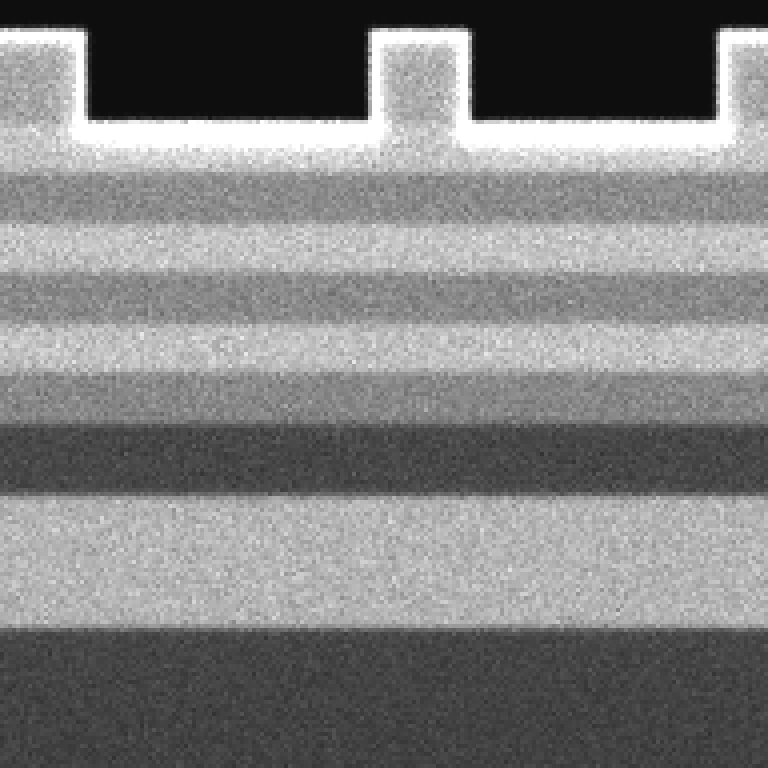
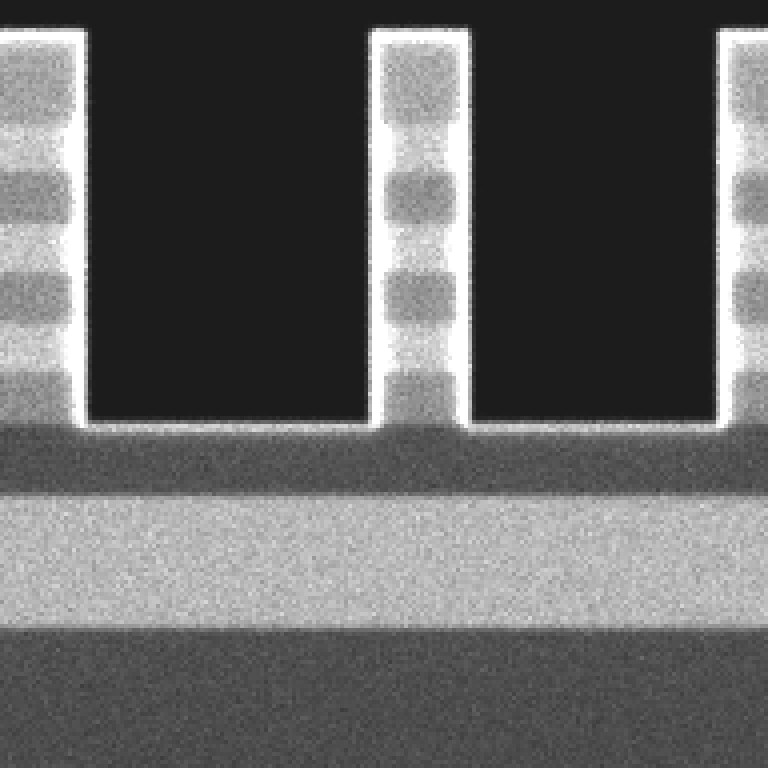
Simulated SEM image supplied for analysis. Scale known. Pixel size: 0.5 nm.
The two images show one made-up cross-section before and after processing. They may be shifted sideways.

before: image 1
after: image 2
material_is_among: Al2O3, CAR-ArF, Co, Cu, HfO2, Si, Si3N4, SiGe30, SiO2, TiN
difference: Al2O3 and Si3N4, removed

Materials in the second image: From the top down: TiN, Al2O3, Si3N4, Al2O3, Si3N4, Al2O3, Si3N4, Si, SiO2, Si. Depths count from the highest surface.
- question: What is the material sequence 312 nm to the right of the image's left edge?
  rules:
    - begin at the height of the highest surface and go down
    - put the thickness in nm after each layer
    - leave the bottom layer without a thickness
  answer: empty 196, Si 36, SiO2 66, Si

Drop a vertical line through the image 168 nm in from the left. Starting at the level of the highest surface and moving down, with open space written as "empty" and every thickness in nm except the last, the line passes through empty 196, Si 36, SiO2 66, Si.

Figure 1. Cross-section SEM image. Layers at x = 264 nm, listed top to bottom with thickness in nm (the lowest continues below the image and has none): empty 196, Si 36, SiO2 66, Si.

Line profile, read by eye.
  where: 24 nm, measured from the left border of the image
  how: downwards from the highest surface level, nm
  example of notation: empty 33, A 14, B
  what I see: TiN 46, Al2O3 24, Si3N4 26, Al2O3 24, Si3N4 26, Al2O3 24, Si3N4 26, Si 36, SiO2 66, Si